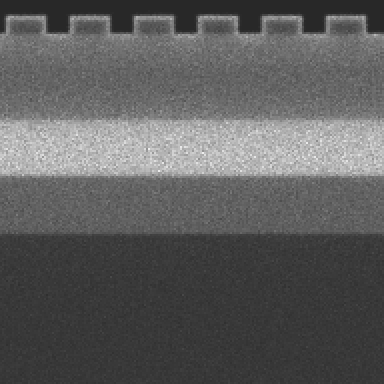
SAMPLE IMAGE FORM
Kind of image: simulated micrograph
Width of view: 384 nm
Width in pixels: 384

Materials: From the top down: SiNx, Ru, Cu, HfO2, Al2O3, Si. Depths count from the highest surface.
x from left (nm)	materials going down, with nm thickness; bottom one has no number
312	empty 18, Ru 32, Cu 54, HfO2 56, Al2O3 58, Si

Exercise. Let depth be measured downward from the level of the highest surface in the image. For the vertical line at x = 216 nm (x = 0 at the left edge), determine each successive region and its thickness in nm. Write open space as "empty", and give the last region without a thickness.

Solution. SiNx 18, Ru 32, Cu 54, HfO2 56, Al2O3 58, Si